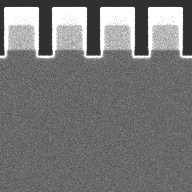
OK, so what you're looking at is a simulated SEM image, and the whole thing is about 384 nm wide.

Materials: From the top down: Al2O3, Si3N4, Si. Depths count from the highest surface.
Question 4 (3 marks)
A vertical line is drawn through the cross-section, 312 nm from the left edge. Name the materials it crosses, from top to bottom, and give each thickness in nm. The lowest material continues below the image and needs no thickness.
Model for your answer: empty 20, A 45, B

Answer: Al2O3 34, Si3N4 50, Si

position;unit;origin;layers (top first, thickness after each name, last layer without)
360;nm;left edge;Al2O3 34, Si3N4 50, Si